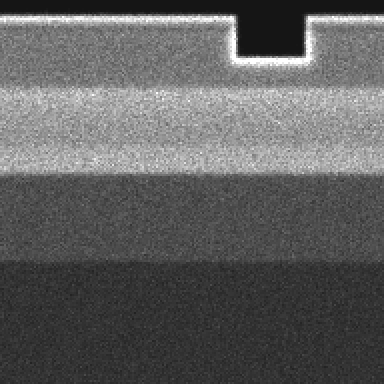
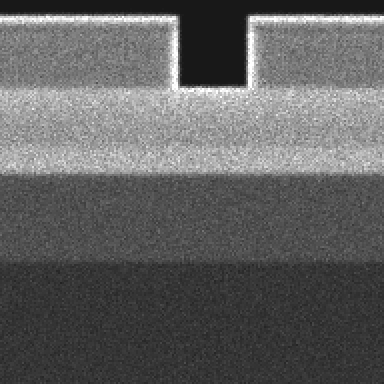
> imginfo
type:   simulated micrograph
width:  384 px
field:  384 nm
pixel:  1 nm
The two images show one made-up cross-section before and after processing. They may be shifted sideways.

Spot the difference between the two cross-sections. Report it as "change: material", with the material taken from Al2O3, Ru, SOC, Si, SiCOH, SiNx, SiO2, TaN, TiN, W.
removed: SiO2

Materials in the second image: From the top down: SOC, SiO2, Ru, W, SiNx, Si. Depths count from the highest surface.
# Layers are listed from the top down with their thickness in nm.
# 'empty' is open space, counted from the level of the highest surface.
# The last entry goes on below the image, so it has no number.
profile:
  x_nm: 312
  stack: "SOC 16, SiO2 56, Ru 58, W 28, SiNx 88, Si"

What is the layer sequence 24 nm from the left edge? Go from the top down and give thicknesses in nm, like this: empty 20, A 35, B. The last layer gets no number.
SOC 16, SiO2 56, Ru 58, W 28, SiNx 88, Si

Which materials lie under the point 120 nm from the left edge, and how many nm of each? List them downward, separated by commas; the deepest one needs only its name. SOC 16, SiO2 56, Ru 58, W 28, SiNx 88, Si